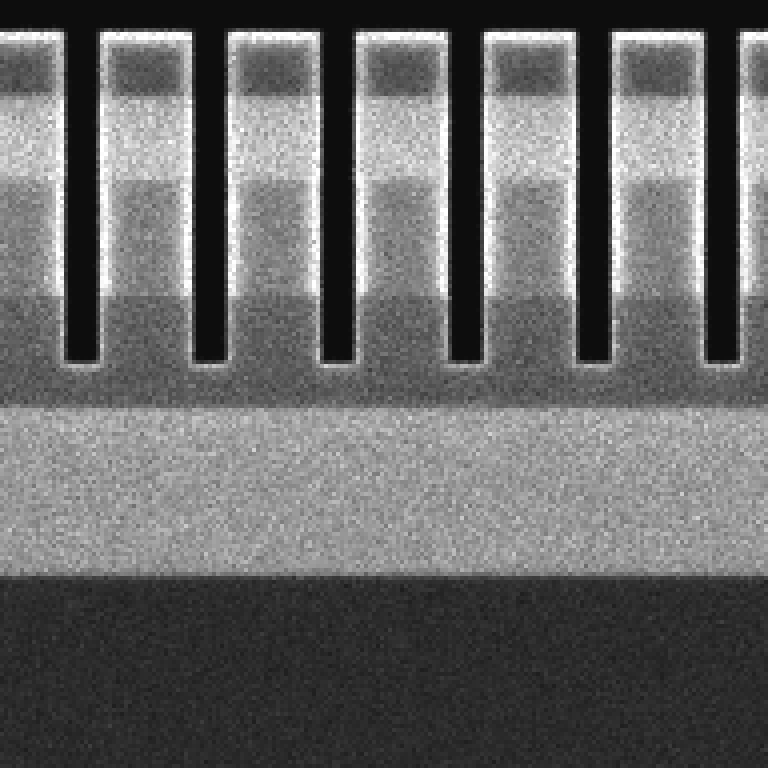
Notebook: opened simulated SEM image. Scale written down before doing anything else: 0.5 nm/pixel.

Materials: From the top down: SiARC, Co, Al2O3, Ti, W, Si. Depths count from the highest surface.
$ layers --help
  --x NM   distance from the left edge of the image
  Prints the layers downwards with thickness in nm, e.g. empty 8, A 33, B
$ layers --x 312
SiARC 32, Co 42, Al2O3 58, Ti 56, W 84, Si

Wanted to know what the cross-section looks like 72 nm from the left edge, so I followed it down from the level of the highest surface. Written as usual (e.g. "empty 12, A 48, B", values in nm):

SiARC 32, Co 42, Al2O3 58, Ti 56, W 84, Si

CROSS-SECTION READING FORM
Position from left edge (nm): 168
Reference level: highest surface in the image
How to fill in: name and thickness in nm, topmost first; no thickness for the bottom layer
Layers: empty 166, Ti 22, W 84, Si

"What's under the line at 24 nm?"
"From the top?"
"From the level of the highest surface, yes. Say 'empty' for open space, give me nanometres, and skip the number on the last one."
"SiARC 32, Co 42, Al2O3 58, Ti 56, W 84, Si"